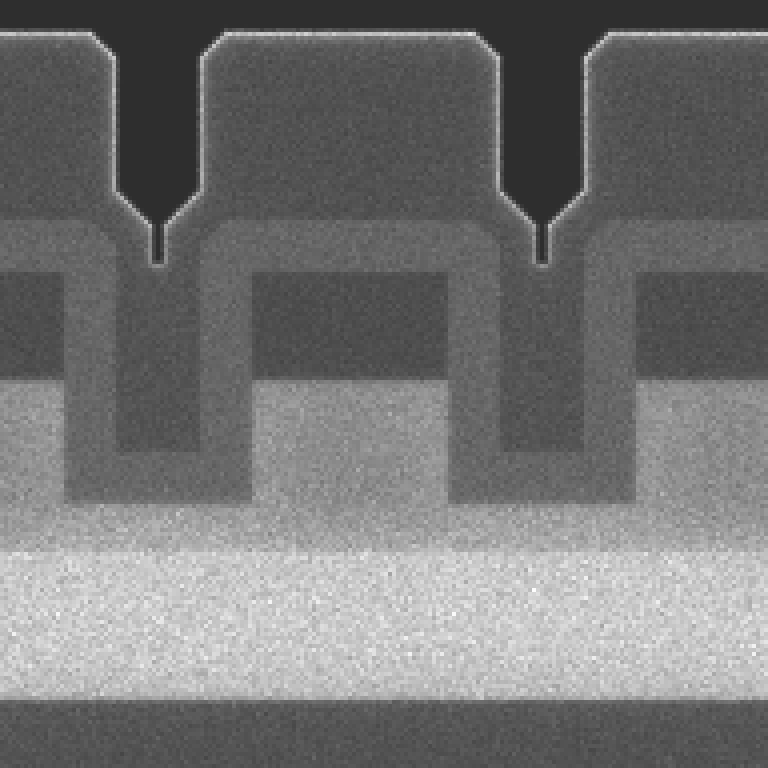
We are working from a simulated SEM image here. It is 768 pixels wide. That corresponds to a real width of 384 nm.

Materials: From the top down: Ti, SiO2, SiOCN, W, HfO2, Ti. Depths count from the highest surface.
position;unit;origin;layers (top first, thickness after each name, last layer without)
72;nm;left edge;empty 94, Ti 116, SiO2 26, W 24, HfO2 74, Ti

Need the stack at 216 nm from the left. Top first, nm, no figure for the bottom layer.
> Ti 94, SiO2 26, SiOCN 54, W 86, HfO2 74, Ti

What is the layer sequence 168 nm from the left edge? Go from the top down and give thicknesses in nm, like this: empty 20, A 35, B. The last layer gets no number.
Ti 94, SiO2 26, SiOCN 54, W 86, HfO2 74, Ti